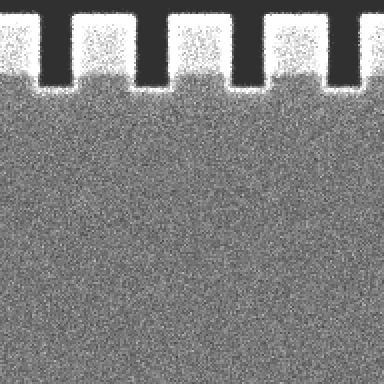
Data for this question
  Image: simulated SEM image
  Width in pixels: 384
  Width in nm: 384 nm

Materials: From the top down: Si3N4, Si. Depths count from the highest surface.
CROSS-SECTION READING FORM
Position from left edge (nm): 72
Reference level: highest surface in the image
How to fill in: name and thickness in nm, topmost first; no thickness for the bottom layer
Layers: empty 72, Si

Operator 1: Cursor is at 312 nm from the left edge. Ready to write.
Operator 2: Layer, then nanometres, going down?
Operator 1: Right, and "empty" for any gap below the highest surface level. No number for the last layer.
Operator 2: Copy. Si3N4 58, Si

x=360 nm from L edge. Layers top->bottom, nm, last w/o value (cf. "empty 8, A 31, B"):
empty 72, Si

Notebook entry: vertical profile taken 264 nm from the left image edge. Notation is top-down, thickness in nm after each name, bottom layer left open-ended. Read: empty 72, Si